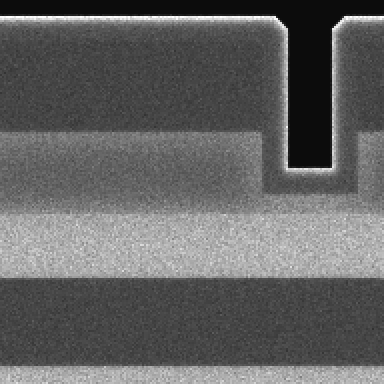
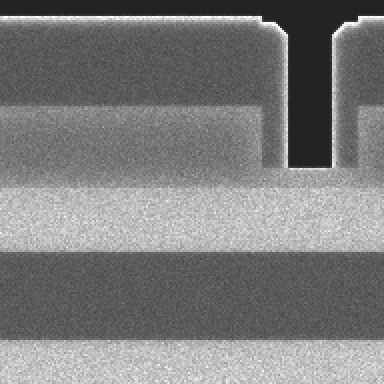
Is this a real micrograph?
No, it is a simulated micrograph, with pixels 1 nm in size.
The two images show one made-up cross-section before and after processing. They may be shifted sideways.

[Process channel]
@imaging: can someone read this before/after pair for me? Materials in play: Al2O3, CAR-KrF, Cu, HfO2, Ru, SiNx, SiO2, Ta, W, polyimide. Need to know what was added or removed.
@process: Al2O3 removed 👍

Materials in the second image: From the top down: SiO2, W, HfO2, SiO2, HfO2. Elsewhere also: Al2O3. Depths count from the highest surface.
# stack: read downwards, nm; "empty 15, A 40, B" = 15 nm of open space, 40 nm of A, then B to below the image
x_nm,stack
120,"SiO2 90, W 82, HfO2 64, SiO2 88, HfO2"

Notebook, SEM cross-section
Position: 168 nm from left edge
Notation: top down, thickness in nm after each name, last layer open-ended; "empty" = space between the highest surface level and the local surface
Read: SiO2 90, W 82, HfO2 64, SiO2 88, HfO2